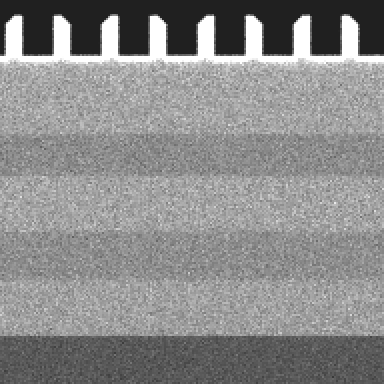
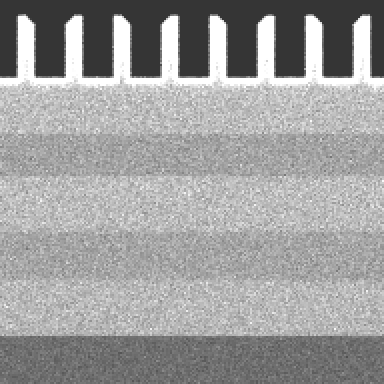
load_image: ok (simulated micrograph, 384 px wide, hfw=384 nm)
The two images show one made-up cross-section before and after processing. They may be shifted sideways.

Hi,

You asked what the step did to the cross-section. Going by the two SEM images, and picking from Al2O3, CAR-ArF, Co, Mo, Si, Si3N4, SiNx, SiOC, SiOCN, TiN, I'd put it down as Si3N4, removed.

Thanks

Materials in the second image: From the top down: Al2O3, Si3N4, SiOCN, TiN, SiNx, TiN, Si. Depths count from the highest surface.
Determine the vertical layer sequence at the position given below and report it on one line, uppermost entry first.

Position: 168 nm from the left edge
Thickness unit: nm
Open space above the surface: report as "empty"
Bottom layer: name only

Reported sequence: empty 2, Al2O3 38, Si3N4 78, SiOCN 42, TiN 56, SiNx 48, TiN 56, Si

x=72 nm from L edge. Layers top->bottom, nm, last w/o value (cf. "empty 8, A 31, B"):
empty 2, Al2O3 38, Si3N4 78, SiOCN 42, TiN 56, SiNx 48, TiN 56, Si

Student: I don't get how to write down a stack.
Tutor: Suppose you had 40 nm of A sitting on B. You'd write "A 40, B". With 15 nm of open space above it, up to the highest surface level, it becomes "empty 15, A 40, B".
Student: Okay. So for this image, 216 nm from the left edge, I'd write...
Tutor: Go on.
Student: Al2O3 40, Si3N4 78, SiOCN 42, TiN 56, SiNx 48, TiN 56, Si